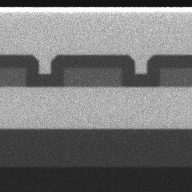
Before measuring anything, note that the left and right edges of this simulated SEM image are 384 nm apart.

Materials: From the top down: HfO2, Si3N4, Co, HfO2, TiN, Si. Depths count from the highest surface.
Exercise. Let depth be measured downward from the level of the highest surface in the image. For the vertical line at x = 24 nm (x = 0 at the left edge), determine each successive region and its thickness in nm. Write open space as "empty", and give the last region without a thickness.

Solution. HfO2 94, Si3N4 26, Co 38, HfO2 84, TiN 76, Si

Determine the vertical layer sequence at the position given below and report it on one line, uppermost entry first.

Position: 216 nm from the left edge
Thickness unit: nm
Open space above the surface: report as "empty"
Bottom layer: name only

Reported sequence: HfO2 94, Si3N4 26, Co 38, HfO2 84, TiN 76, Si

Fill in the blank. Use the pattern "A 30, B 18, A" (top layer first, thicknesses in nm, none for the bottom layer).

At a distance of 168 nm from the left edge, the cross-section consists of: HfO2 94, Si3N4 26, Co 38, HfO2 84, TiN 76, Si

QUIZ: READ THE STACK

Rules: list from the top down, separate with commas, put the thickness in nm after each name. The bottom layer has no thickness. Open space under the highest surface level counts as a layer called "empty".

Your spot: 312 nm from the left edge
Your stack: HfO2 94, Si3N4 64, HfO2 84, TiN 76, Si